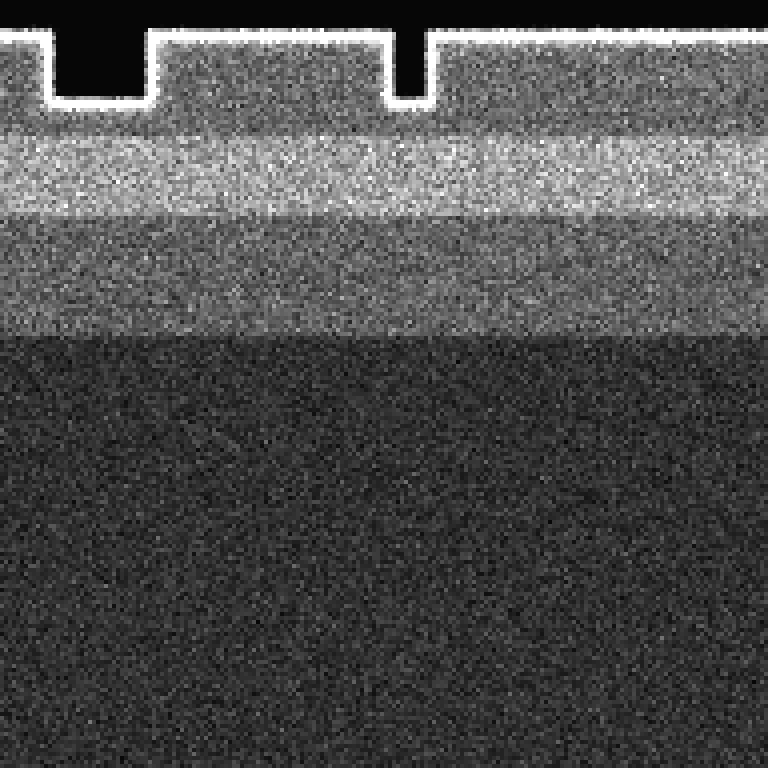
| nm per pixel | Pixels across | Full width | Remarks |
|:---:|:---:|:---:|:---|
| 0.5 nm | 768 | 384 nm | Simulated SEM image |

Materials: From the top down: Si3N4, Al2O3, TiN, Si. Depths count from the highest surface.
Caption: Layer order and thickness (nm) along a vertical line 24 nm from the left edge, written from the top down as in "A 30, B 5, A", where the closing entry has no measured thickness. Si3N4 52, Al2O3 40, TiN 60, Si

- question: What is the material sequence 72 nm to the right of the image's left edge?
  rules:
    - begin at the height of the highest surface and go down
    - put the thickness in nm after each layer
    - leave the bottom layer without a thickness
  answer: empty 34, Si3N4 18, Al2O3 40, TiN 60, Si